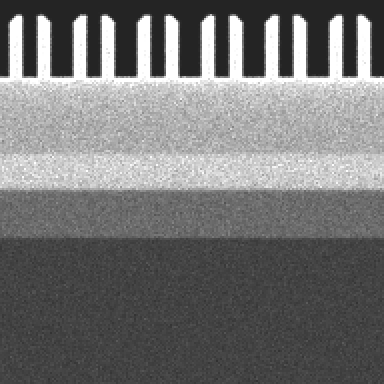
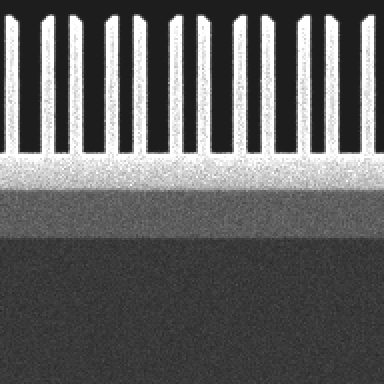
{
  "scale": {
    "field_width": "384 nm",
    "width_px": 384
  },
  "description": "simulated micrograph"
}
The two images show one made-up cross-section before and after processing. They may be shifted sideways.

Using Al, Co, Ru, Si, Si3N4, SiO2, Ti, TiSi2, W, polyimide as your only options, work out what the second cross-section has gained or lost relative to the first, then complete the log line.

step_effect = removed Ru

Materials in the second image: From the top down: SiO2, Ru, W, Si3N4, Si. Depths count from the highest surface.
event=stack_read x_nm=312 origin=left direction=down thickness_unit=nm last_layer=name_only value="empty 138, W 36, Si3N4 48, Si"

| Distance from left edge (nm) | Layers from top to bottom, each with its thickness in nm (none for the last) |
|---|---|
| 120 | empty 138, W 36, Si3N4 48, Si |